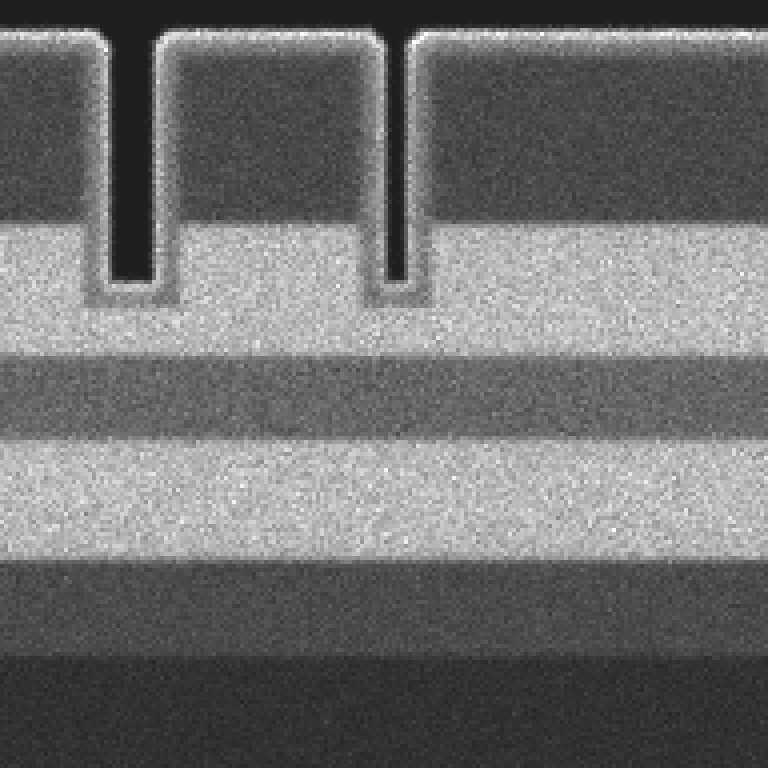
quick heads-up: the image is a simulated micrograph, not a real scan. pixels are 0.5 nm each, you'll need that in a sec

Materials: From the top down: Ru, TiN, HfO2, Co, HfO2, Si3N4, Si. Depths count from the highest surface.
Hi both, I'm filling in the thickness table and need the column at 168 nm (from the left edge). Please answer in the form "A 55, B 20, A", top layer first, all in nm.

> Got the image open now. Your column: Ru 12, TiN 84, HfO2 66, Co 42, HfO2 60, Si3N4 48, Si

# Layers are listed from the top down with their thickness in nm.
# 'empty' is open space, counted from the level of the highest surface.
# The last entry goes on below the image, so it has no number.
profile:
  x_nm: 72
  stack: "empty 126, Ru 12, HfO2 24, Co 42, HfO2 60, Si3N4 48, Si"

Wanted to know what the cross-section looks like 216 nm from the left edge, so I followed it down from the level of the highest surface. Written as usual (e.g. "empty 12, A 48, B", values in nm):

Ru 12, TiN 84, HfO2 66, Co 42, HfO2 60, Si3N4 48, Si